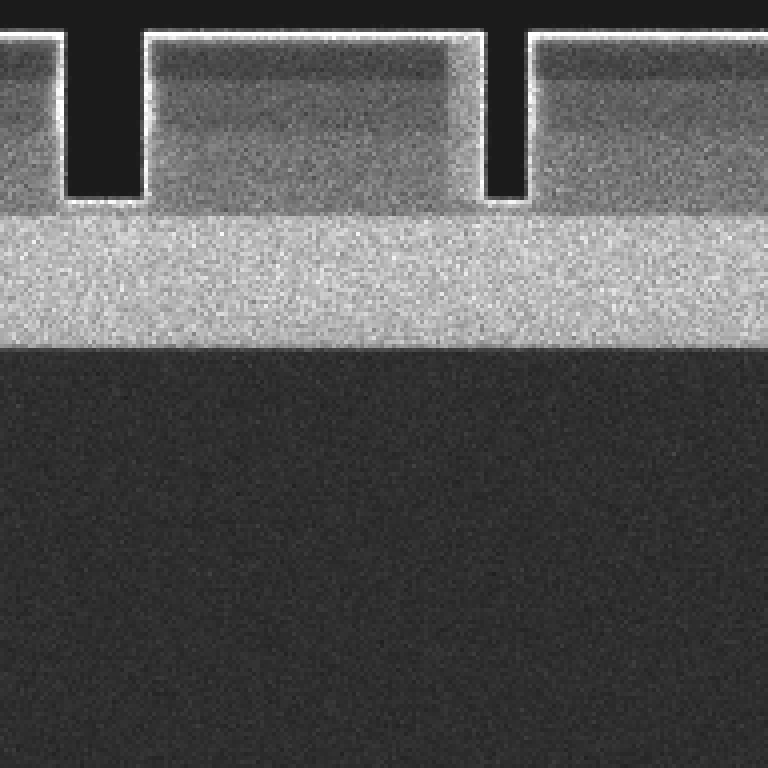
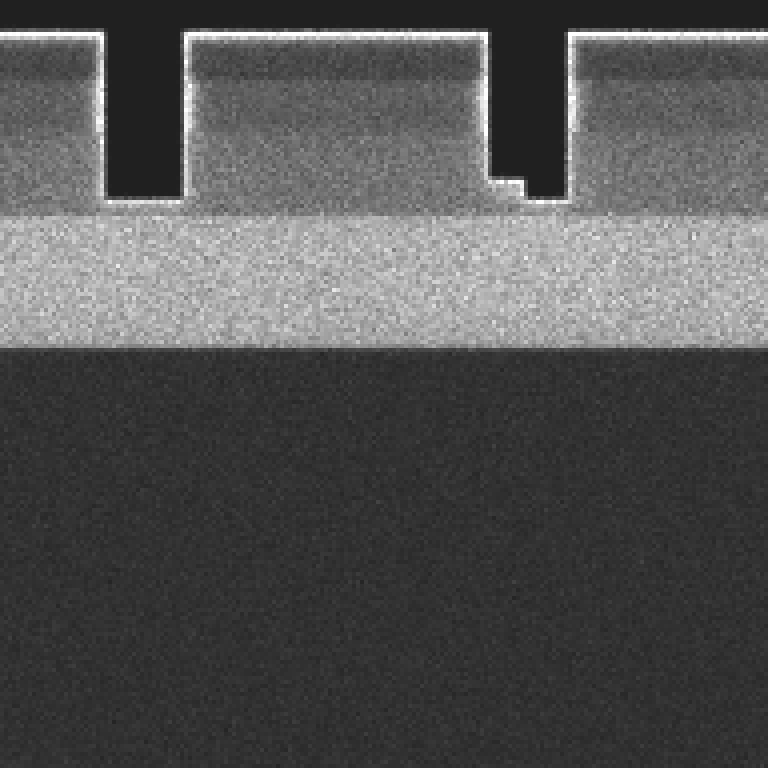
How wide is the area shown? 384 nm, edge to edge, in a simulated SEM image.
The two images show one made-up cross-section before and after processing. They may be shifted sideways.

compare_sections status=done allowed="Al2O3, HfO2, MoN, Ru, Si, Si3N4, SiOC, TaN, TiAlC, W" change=removed material="W"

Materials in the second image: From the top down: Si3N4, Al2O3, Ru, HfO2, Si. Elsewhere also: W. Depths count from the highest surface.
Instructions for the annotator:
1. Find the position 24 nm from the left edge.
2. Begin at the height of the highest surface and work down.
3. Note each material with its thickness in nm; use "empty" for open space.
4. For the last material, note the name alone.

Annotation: Si3N4 24, Al2O3 26, Ru 42, HfO2 66, Si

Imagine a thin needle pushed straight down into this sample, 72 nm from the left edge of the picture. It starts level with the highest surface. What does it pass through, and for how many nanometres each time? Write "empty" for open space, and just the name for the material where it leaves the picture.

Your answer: empty 84, Ru 8, HfO2 66, Si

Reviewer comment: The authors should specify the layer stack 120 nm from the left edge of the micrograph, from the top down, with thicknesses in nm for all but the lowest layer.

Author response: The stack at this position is Si3N4 24, Al2O3 26, Ru 42, HfO2 66, Si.